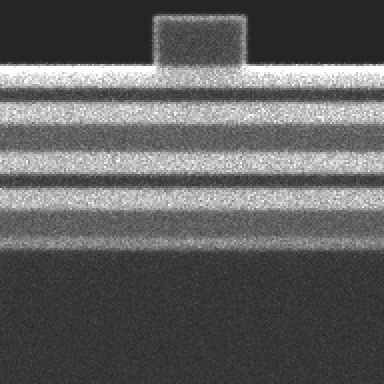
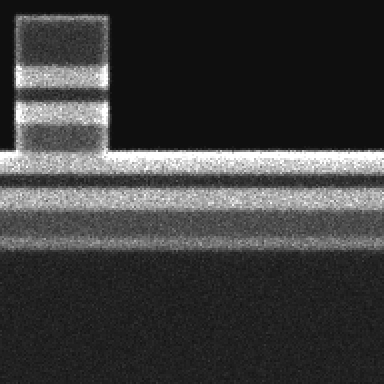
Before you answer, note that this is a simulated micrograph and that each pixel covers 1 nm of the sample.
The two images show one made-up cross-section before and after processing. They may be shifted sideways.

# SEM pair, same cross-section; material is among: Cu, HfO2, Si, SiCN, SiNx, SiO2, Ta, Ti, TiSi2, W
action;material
removed;HfO2 and Si and SiO2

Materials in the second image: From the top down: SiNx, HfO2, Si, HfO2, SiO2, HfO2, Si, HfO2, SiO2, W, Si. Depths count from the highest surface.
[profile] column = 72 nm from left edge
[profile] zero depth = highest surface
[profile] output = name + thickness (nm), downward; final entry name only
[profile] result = SiNx 50, HfO2 22, Si 14, HfO2 22, SiO2 28, HfO2 22, Si 14, HfO2 22, SiO2 28, W 12, Si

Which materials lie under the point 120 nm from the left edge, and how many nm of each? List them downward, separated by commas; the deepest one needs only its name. empty 136, HfO2 22, Si 14, HfO2 22, SiO2 28, W 12, Si